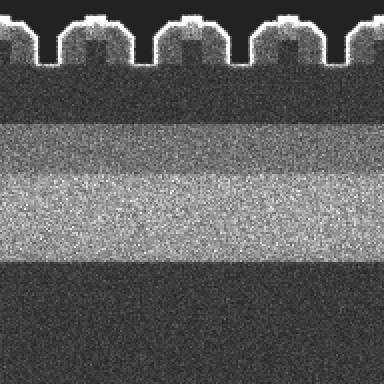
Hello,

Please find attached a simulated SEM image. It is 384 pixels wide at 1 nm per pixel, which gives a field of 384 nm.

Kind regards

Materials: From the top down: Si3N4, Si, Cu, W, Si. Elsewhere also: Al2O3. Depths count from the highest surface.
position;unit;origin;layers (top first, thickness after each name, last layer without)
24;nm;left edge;empty 8, Si3N4 40, Si 60, Cu 50, W 88, Si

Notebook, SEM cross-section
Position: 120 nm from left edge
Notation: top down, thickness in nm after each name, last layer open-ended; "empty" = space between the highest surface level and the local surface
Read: empty 8, Si3N4 40, Si 60, Cu 50, W 88, Si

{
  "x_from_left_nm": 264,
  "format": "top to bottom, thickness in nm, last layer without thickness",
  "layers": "empty 6, Si3N4 42, Si 60, Cu 50, W 88, Si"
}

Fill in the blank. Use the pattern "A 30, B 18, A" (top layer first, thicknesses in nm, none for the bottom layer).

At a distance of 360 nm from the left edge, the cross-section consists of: empty 6, Si3N4 42, Si 60, Cu 50, W 88, Si